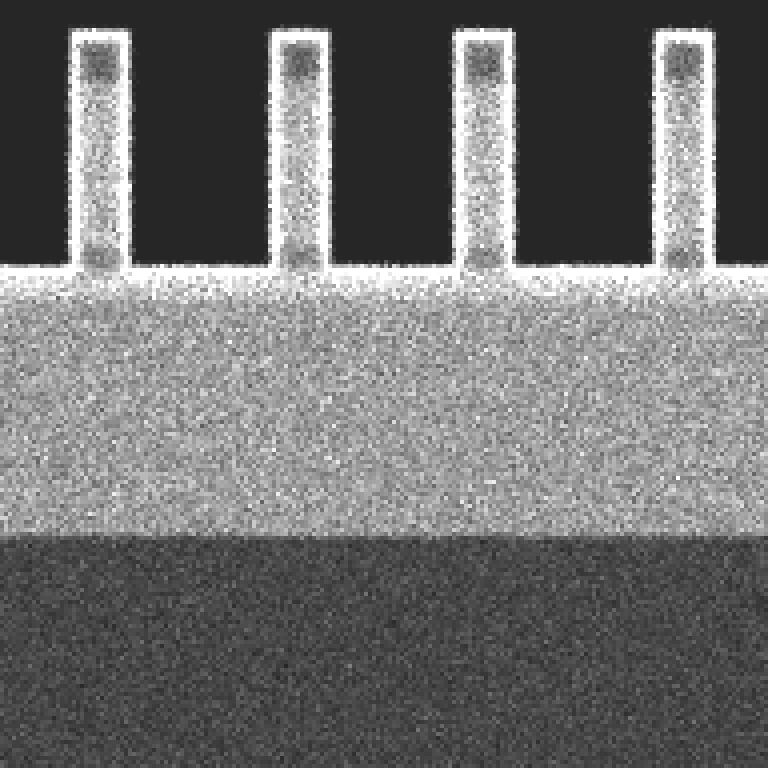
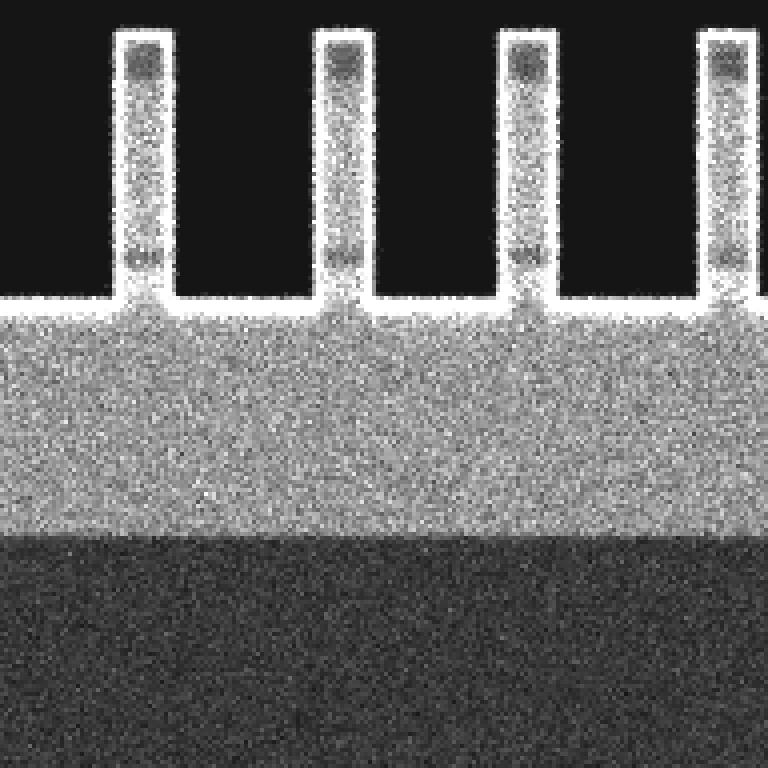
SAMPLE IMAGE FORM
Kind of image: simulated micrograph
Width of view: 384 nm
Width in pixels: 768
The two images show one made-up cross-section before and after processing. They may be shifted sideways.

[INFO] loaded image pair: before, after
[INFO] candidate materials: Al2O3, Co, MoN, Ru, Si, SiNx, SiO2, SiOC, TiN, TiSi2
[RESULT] removed Ru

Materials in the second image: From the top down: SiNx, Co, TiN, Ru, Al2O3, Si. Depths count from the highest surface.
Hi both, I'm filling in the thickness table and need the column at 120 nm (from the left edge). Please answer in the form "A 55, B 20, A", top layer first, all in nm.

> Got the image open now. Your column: empty 134, Al2O3 118, Si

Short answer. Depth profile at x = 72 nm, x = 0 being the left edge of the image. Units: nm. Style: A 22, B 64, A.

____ SiNx 24, Co 84, TiN 10, Ru 16, Al2O3 118, Si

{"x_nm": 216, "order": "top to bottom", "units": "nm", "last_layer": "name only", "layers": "empty 134, Al2O3 118, Si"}